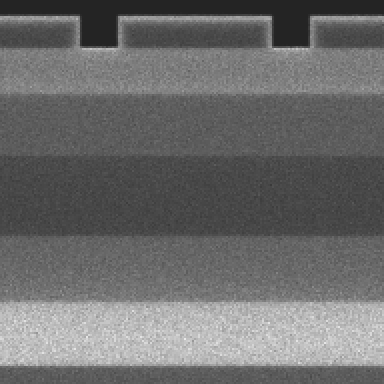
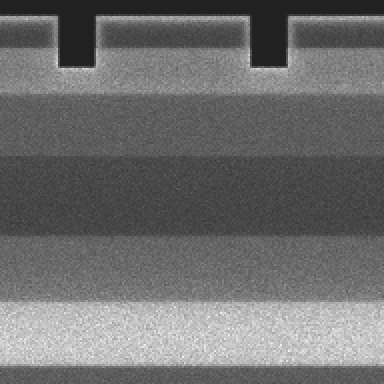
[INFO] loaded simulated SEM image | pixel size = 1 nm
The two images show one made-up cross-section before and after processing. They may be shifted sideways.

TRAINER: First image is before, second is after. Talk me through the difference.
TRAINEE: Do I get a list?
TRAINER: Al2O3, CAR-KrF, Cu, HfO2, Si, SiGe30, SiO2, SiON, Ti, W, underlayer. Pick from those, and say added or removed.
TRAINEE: removed: W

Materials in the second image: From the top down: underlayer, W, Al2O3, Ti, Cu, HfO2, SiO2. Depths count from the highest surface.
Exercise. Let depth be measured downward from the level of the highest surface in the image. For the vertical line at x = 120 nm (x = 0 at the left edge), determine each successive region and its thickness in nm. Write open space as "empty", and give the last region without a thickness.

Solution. underlayer 32, W 46, Al2O3 62, Ti 80, Cu 66, HfO2 64, SiO2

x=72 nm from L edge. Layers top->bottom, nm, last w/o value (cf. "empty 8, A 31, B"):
empty 52, W 26, Al2O3 62, Ti 80, Cu 66, HfO2 64, SiO2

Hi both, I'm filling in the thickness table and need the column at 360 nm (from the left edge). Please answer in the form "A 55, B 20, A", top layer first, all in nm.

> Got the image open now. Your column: underlayer 32, W 46, Al2O3 62, Ti 80, Cu 66, HfO2 64, SiO2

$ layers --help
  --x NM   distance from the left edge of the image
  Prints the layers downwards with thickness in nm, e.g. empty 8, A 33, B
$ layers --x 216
underlayer 32, W 46, Al2O3 62, Ti 80, Cu 66, HfO2 64, SiO2